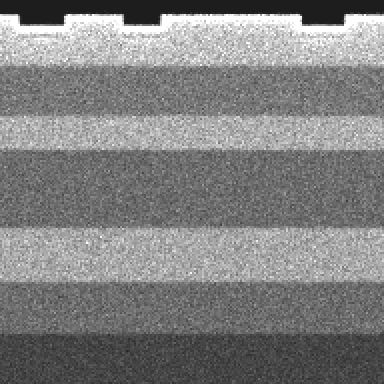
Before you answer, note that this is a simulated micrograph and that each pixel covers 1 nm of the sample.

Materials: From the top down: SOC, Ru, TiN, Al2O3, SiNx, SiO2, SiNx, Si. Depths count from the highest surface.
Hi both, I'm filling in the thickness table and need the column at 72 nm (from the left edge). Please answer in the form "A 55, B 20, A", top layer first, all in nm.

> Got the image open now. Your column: Ru 50, TiN 50, Al2O3 34, SiNx 78, SiO2 54, SiNx 52, Si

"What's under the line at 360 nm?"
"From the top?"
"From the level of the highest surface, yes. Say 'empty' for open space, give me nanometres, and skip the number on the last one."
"Ru 50, TiN 50, Al2O3 34, SiNx 78, SiO2 54, SiNx 52, Si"